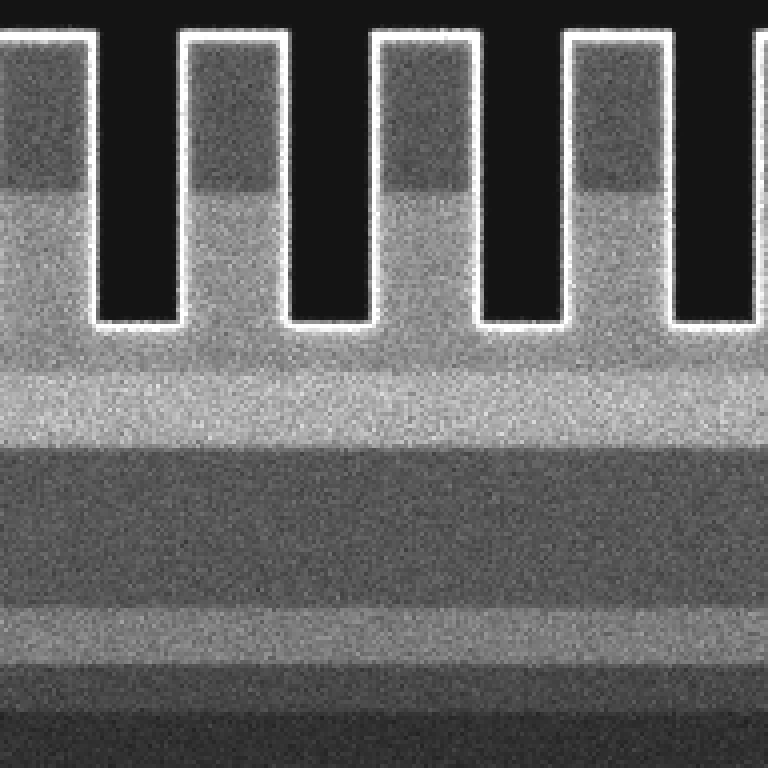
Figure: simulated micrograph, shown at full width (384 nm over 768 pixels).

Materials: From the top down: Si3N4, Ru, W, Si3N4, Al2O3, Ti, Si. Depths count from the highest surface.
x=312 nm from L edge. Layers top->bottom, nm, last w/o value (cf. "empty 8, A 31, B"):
Si3N4 80, Ru 90, W 38, Si3N4 80, Al2O3 28, Ti 24, Si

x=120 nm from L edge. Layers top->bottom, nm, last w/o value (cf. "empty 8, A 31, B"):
Si3N4 80, Ru 90, W 38, Si3N4 80, Al2O3 28, Ti 24, Si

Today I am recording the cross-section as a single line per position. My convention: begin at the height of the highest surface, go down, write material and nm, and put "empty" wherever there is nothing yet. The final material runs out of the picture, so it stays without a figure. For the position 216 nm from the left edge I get Si3N4 80, Ru 90, W 38, Si3N4 80, Al2O3 28, Ti 24, Si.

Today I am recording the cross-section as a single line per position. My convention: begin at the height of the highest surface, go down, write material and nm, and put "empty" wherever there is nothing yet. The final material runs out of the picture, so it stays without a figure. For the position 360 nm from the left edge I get empty 146, Ru 24, W 38, Si3N4 80, Al2O3 28, Ti 24, Si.